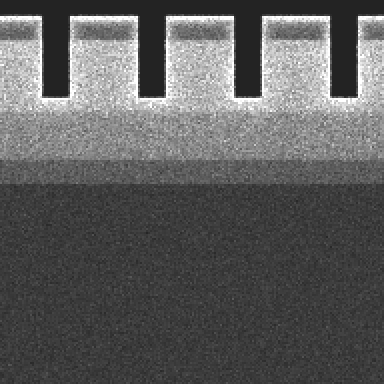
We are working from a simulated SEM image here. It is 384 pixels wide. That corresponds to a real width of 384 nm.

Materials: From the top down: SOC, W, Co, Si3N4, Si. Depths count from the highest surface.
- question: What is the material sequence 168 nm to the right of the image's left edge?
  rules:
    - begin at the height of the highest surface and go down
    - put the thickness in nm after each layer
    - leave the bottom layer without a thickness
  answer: SOC 24, W 72, Co 48, Si3N4 24, Si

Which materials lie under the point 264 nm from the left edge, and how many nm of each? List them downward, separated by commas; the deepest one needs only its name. SOC 24, W 72, Co 48, Si3N4 24, Si